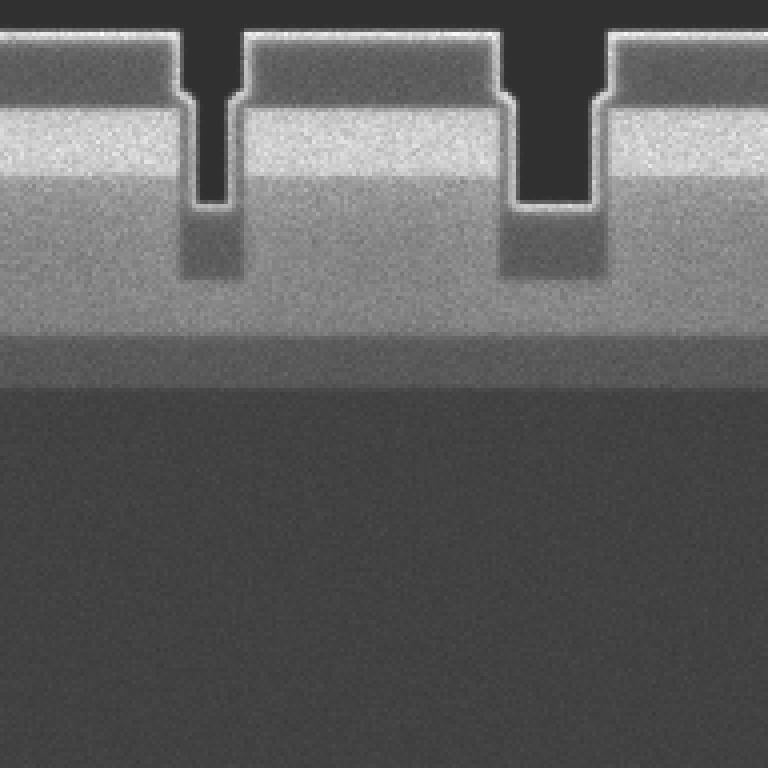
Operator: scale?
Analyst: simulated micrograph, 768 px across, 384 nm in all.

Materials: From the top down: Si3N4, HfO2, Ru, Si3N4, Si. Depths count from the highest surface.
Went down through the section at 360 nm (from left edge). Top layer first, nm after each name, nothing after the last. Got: Si3N4 38, HfO2 34, Ru 80, Si3N4 26, Si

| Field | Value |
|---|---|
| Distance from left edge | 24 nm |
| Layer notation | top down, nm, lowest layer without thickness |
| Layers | Si3N4 38, HfO2 34, Ru 80, Si3N4 26, Si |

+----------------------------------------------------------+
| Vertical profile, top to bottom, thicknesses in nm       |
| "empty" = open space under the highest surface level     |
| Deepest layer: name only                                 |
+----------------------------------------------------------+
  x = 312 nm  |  Si3N4 38, HfO2 34, Ru 80, Si3N4 26, Si